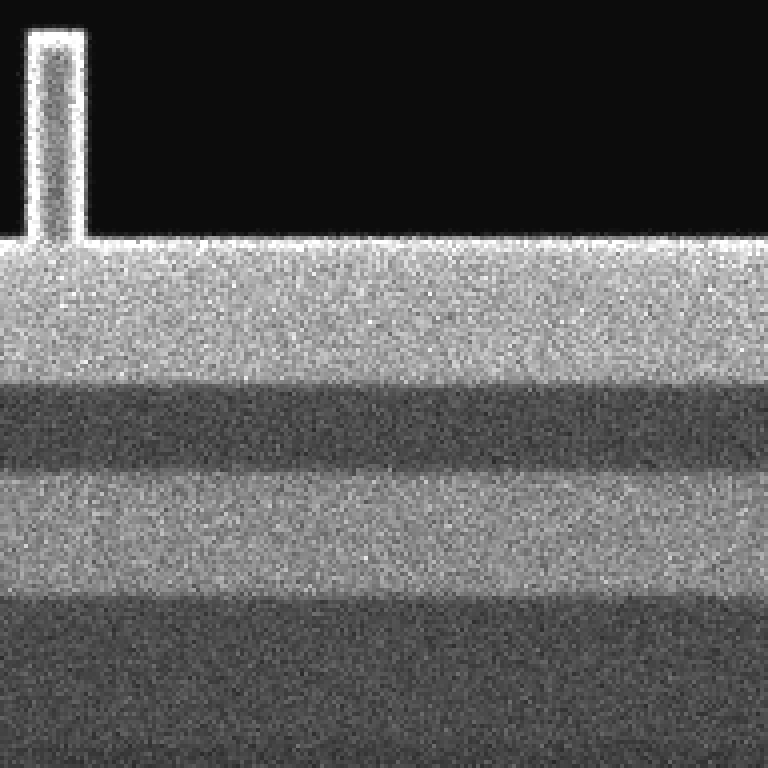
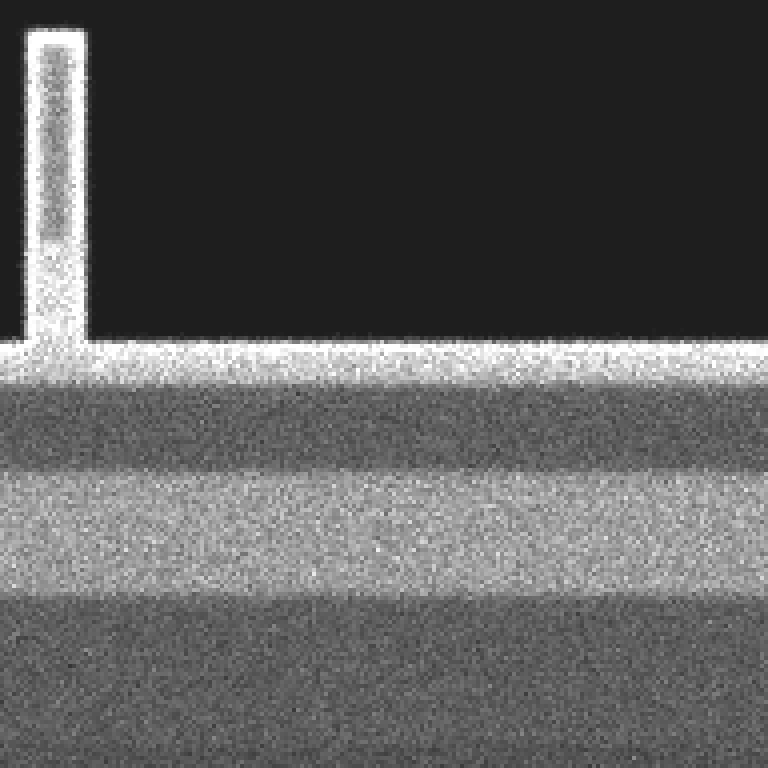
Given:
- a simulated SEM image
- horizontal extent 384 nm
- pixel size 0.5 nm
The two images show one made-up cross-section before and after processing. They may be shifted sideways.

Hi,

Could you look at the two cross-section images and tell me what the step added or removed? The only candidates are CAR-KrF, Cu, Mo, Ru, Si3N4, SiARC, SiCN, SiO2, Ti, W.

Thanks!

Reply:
removed W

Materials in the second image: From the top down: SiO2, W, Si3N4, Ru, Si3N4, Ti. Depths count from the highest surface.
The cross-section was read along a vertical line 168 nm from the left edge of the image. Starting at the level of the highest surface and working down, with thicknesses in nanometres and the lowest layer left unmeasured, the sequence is empty 156, W 20, Si3N4 44, Ru 62, Si3N4 74, Ti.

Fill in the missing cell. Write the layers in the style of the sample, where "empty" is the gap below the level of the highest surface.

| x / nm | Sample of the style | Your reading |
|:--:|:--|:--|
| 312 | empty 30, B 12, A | empty 156, W 20, Si3N4 44, Ru 62, Si3N4 74, Ti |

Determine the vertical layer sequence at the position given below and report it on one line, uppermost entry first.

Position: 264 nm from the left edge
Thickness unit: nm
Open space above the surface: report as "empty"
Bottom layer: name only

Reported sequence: empty 156, W 20, Si3N4 44, Ru 62, Si3N4 74, Ti